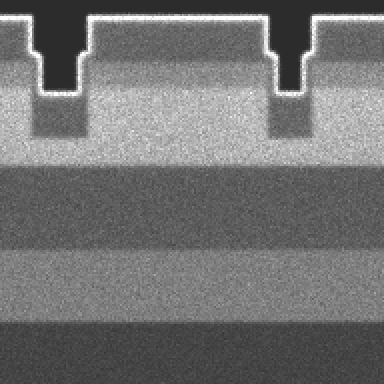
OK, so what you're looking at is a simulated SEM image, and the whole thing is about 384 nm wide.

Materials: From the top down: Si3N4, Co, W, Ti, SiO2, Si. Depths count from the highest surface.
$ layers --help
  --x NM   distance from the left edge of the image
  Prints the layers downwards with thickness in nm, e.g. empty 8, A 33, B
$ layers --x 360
Si3N4 46, Co 26, W 78, Ti 84, SiO2 72, Si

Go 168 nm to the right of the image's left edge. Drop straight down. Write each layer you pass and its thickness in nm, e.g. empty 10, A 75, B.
Si3N4 46, Co 26, W 78, Ti 84, SiO2 72, Si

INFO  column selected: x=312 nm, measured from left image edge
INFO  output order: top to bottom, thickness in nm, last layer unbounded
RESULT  Si3N4 46, Co 26, W 78, Ti 84, SiO2 72, Si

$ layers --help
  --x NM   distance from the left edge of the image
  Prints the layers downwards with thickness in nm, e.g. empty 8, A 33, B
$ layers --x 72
empty 76, Si3N4 46, W 28, Ti 84, SiO2 72, Si